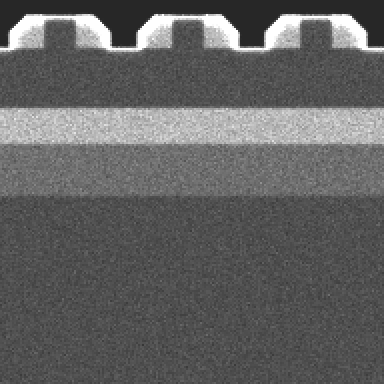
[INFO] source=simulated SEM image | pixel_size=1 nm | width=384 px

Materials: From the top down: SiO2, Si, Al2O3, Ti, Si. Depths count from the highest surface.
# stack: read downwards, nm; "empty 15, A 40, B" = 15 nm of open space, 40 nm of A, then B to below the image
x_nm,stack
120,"empty 32, Si 60, Al2O3 36, Ti 52, Si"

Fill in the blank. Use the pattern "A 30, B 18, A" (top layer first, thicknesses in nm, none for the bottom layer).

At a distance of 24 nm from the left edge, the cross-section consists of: empty 2, SiO2 30, Si 60, Al2O3 36, Ti 52, Si